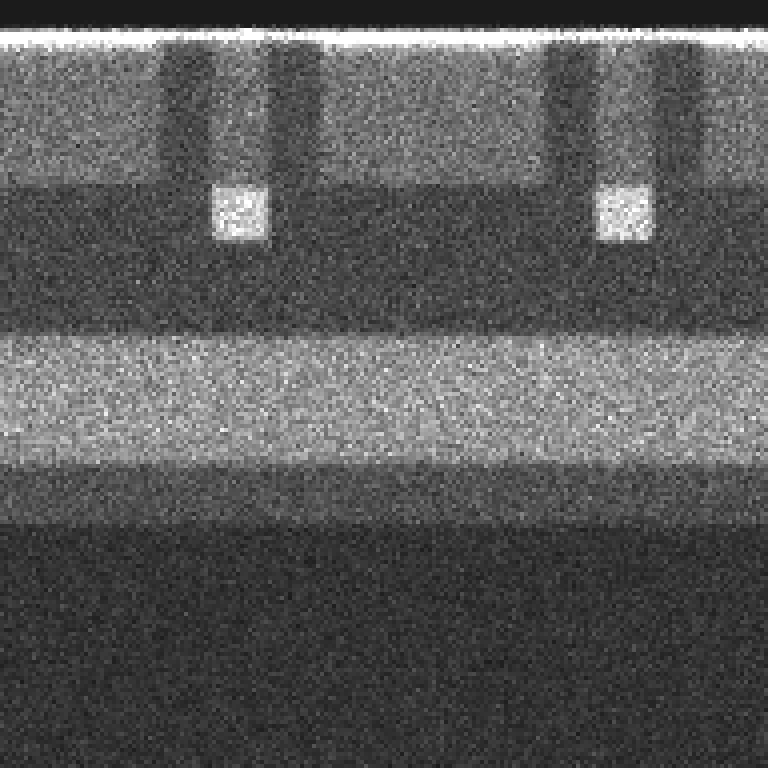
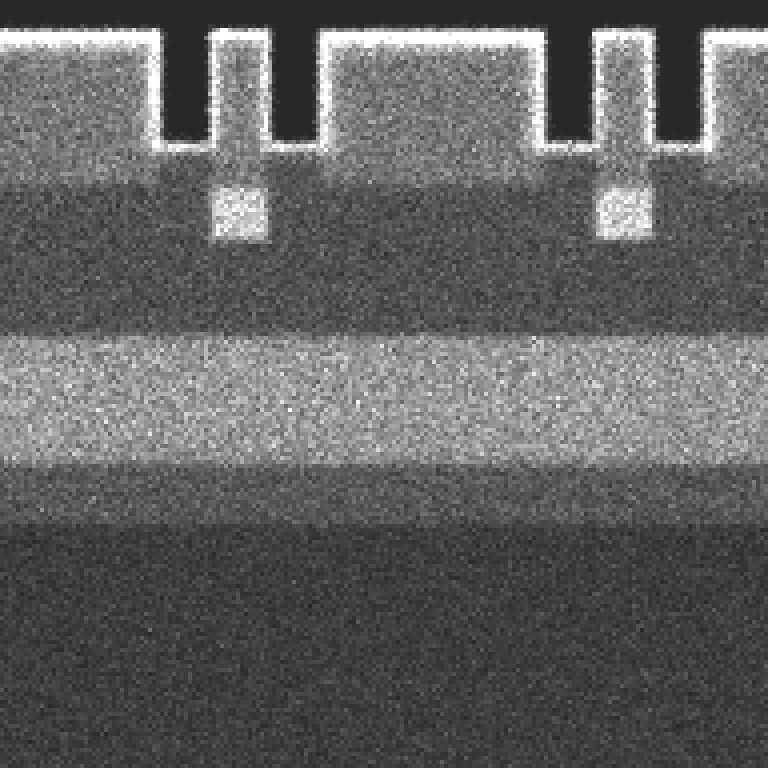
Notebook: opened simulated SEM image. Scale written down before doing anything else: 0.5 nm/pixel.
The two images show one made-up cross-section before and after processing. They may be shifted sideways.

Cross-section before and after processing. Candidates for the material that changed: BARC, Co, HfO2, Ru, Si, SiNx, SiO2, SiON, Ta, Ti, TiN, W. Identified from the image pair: SiNx (removed).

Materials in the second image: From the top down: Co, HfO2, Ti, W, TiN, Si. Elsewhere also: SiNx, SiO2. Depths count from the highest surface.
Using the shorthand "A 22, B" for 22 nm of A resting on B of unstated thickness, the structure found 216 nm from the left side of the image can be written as SiO2 76, Ti 76, W 64, TiN 30, Si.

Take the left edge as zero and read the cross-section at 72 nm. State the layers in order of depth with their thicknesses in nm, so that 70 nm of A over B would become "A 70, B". SiO2 76, Ti 76, W 64, TiN 30, Si